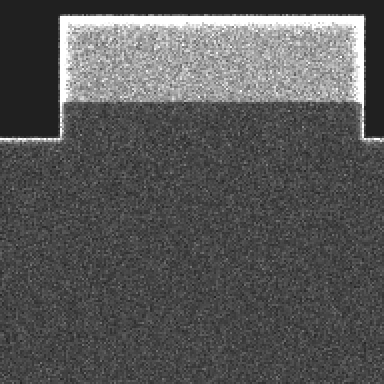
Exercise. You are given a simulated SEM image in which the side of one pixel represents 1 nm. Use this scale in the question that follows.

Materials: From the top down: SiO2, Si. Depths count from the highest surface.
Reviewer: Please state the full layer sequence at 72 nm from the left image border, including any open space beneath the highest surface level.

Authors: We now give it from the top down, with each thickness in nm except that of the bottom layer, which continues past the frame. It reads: SiO2 86, Si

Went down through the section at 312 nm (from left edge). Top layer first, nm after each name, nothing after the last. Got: SiO2 86, Si